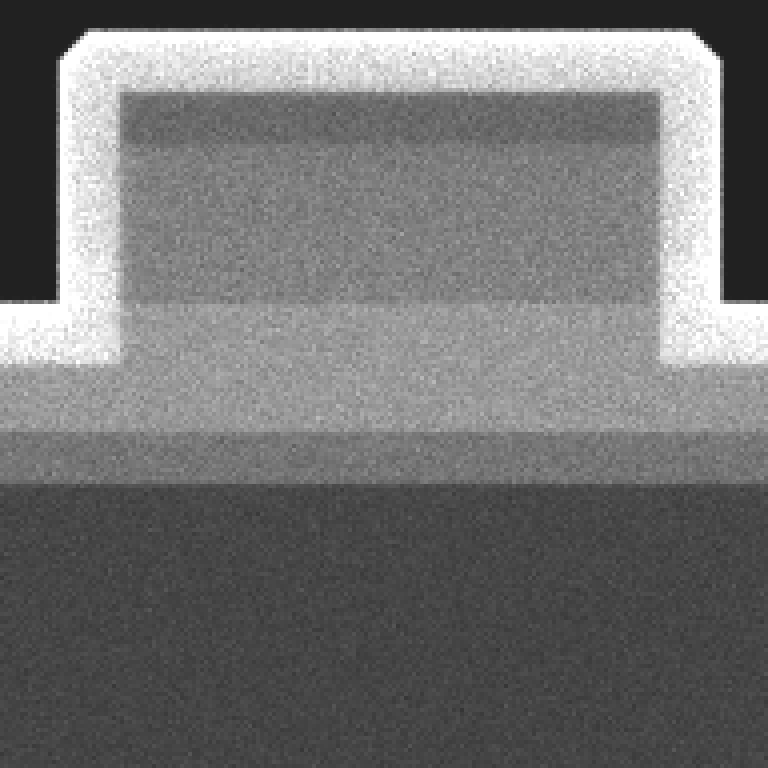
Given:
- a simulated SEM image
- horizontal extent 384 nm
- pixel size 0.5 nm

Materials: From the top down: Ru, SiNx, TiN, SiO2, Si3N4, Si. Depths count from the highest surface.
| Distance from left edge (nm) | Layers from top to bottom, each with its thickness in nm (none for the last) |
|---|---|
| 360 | empty 136, Ru 30, SiO2 34, Si3N4 26, Si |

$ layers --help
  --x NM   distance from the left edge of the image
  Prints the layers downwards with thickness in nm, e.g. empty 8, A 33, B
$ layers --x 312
Ru 30, SiNx 26, TiN 80, SiO2 64, Si3N4 26, Si